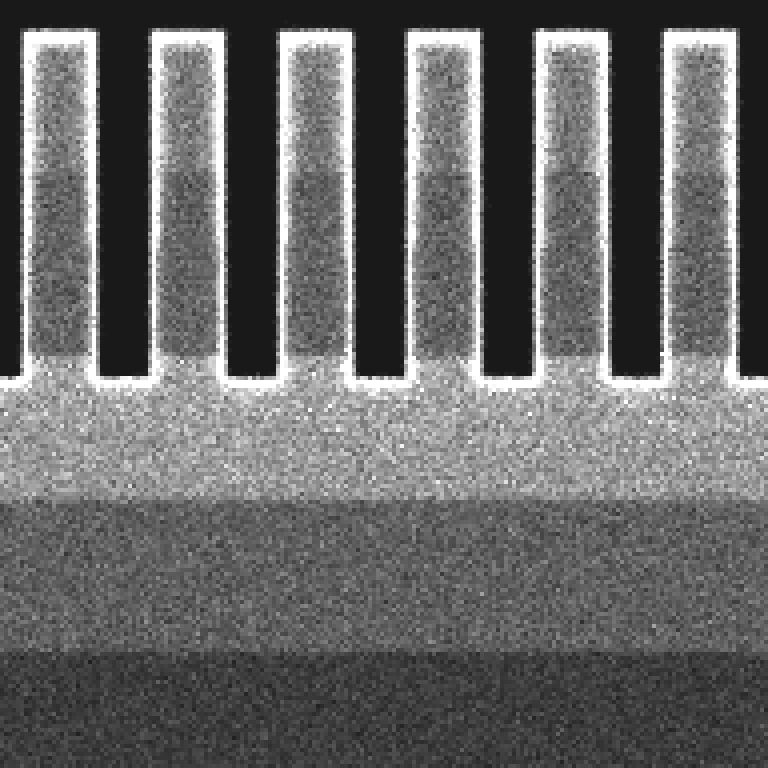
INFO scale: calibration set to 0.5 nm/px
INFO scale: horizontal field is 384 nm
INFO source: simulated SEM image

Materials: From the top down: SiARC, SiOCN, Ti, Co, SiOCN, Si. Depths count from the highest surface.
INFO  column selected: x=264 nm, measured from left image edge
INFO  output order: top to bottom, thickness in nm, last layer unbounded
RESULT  empty 174, Co 60, SiOCN 76, Si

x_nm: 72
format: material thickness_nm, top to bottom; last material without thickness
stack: empty 174, Co 60, SiOCN 76, Si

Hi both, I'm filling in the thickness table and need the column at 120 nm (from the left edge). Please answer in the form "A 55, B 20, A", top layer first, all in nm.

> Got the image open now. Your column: empty 174, Co 60, SiOCN 76, Si